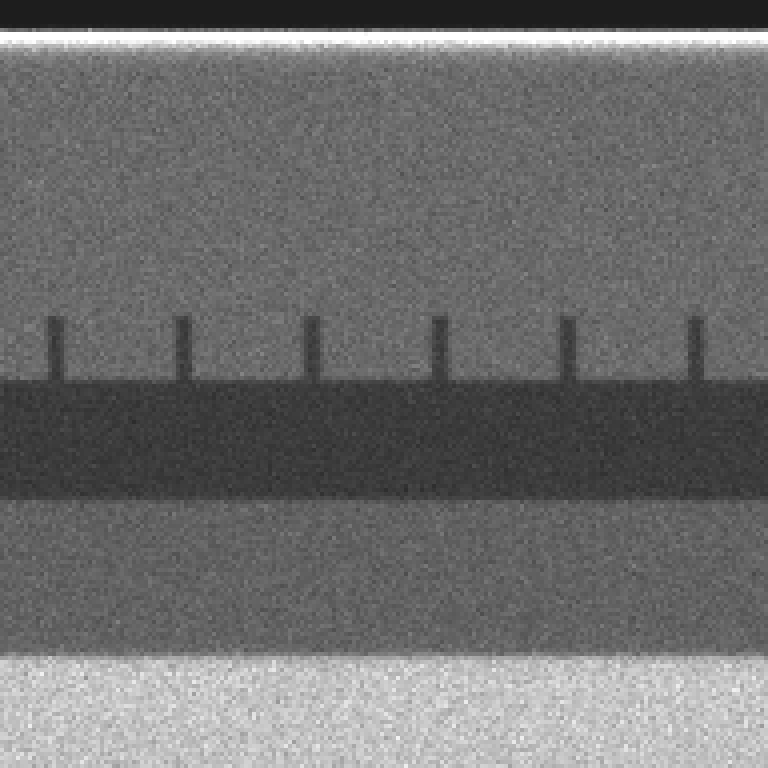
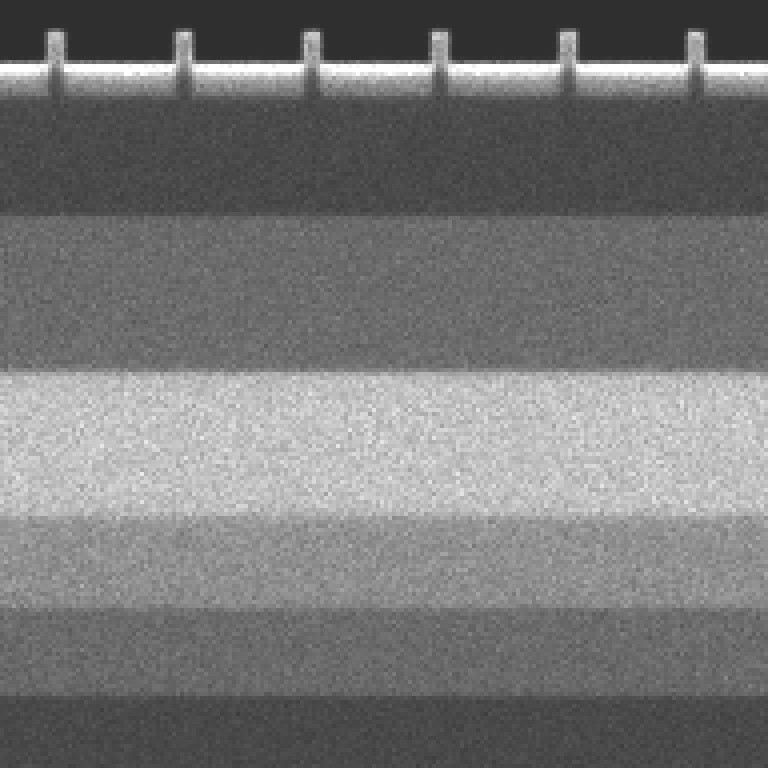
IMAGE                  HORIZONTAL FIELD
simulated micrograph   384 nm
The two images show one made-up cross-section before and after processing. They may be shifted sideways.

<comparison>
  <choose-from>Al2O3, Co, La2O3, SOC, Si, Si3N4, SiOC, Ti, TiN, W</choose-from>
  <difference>SOC removed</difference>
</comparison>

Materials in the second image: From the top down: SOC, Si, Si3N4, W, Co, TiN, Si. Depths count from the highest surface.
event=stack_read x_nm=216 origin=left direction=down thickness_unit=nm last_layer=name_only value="Si 92, Si3N4 78, W 72, Co 46, TiN 44, Si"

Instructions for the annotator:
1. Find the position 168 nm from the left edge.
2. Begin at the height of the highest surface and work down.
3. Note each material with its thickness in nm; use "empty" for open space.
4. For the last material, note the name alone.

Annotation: empty 16, SOC 16, Si 60, Si3N4 78, W 72, Co 46, TiN 44, Si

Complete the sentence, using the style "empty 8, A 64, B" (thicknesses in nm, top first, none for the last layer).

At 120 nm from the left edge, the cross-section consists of empty 16, SOC 16, Si 60, Si3N4 78, W 72, Co 46, TiN 44, Si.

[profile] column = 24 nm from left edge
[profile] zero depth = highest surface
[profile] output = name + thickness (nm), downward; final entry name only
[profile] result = Si 92, Si3N4 78, W 72, Co 46, TiN 44, Si